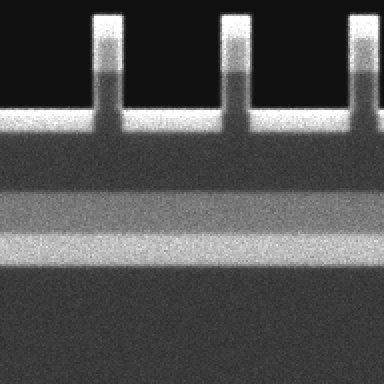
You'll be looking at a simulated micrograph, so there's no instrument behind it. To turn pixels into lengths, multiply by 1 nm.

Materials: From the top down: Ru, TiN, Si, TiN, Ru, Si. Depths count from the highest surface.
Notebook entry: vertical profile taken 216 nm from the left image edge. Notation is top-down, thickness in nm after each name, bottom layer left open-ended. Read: empty 94, Ru 22, Si 60, TiN 42, Ru 32, Si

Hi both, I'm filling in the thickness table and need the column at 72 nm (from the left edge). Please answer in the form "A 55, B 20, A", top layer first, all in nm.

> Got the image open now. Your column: empty 94, Ru 22, Si 60, TiN 42, Ru 32, Si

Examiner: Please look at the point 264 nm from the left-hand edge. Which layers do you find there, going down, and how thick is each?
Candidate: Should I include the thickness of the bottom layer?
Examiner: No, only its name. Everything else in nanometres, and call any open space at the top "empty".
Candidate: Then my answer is empty 94, Ru 22, Si 60, TiN 42, Ru 32, Si